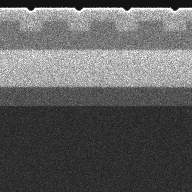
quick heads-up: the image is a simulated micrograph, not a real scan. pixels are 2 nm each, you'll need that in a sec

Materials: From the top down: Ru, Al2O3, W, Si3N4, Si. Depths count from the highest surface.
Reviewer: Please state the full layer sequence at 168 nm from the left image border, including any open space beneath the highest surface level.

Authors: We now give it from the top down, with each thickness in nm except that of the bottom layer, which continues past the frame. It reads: Ru 46, Al2O3 38, W 74, Si3N4 38, Si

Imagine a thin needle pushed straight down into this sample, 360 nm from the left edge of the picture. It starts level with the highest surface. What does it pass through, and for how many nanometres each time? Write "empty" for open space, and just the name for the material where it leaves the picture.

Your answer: Ru 46, Al2O3 38, W 74, Si3N4 38, Si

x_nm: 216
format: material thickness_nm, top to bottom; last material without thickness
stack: Ru 26, Al2O3 58, W 74, Si3N4 38, Si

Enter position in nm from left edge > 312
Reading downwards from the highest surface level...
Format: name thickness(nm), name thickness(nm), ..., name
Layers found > Ru 26, Al2O3 58, W 74, Si3N4 38, Si